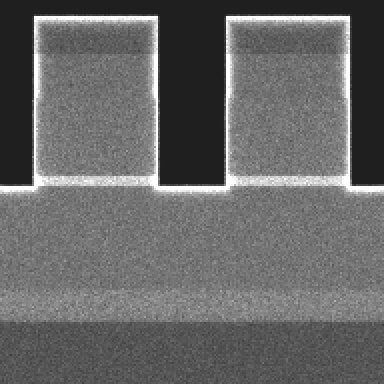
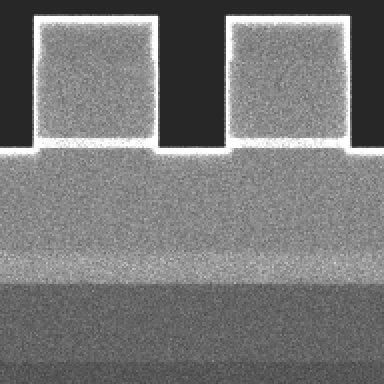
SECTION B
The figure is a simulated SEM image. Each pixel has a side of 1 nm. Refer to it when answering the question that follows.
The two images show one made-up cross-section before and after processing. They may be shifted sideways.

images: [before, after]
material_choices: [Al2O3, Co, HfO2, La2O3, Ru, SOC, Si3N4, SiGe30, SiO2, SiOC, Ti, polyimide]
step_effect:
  removed: SOC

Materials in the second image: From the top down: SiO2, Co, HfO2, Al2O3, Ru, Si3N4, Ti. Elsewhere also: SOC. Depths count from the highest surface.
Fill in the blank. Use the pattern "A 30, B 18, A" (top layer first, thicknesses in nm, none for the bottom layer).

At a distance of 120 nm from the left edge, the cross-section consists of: SiO2 44, Co 78, HfO2 10, Al2O3 104, Ru 32, Si3N4 78, Ti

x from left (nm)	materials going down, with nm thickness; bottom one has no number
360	empty 132, Al2O3 104, Ru 32, Si3N4 78, Ti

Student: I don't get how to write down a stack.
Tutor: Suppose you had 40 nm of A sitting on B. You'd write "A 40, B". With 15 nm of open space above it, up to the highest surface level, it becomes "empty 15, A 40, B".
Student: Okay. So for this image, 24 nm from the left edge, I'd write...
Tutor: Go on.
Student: empty 132, Al2O3 104, Ru 32, Si3N4 78, Ti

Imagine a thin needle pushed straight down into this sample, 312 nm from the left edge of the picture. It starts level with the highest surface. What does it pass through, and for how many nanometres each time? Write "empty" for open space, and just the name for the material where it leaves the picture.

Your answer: SiO2 44, Co 78, HfO2 10, Al2O3 104, Ru 32, Si3N4 78, Ti